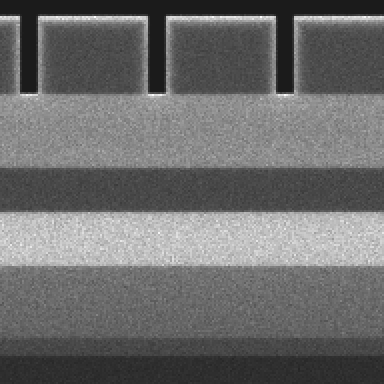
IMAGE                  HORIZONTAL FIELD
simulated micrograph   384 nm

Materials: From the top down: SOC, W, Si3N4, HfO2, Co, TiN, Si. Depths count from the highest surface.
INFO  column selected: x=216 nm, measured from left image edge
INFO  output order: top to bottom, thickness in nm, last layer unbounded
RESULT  SOC 78, W 74, Si3N4 44, HfO2 54, Co 72, TiN 18, Si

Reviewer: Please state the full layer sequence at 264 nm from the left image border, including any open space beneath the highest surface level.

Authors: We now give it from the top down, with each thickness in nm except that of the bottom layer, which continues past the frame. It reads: SOC 78, W 74, Si3N4 44, HfO2 54, Co 72, TiN 18, Si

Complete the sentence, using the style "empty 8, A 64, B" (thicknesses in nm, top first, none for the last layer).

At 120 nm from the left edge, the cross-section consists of SOC 78, W 74, Si3N4 44, HfO2 54, Co 72, TiN 18, Si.